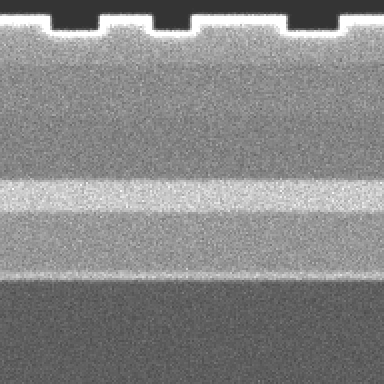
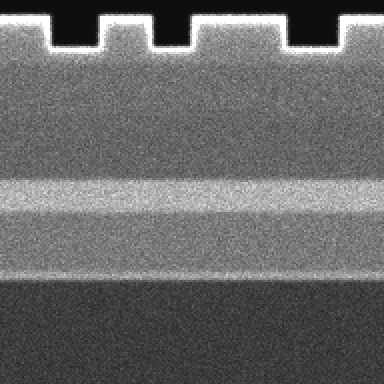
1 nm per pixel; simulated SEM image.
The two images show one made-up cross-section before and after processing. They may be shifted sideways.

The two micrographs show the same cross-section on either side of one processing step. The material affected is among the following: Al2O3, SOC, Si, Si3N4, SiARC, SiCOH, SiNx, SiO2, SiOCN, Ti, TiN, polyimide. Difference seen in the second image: TiN removed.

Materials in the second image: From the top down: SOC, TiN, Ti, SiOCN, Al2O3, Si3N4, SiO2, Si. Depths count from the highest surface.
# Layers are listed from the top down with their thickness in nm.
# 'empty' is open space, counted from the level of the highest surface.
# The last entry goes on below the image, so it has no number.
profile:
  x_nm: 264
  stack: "SOC 16, TiN 32, Ti 52, SiOCN 64, Al2O3 32, Si3N4 60, SiO2 8, Si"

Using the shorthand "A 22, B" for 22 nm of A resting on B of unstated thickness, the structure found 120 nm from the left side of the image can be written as SOC 16, TiN 32, Ti 52, SiOCN 64, Al2O3 32, Si3N4 60, SiO2 8, Si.